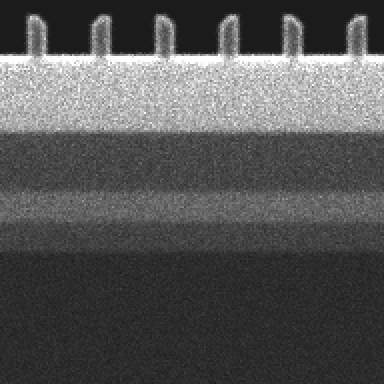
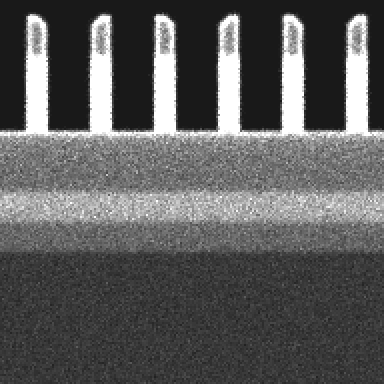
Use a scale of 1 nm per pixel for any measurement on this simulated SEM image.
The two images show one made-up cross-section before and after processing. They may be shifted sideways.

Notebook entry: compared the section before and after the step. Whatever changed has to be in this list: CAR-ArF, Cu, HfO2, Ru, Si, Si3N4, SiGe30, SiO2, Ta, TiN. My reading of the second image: HfO2 removed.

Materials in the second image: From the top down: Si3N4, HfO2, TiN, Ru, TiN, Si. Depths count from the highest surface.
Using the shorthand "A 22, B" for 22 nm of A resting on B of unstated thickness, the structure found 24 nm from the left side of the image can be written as empty 116, TiN 60, Ru 30, TiN 30, Si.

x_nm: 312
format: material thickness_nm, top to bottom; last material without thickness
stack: empty 116, TiN 60, Ru 30, TiN 30, Si